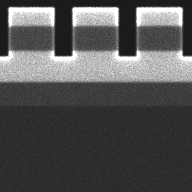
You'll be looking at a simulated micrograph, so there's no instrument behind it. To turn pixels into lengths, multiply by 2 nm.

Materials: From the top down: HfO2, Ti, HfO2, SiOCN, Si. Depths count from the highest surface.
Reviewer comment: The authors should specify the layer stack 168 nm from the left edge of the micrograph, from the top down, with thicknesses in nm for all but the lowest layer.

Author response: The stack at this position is HfO2 36, Ti 50, HfO2 62, SiOCN 48, Si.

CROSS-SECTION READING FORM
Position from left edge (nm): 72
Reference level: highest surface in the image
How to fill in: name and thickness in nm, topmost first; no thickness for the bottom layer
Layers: HfO2 36, Ti 50, HfO2 62, SiOCN 48, Si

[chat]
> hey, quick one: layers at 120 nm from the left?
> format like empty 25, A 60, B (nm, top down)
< empty 98, HfO2 50, SiOCN 48, Si